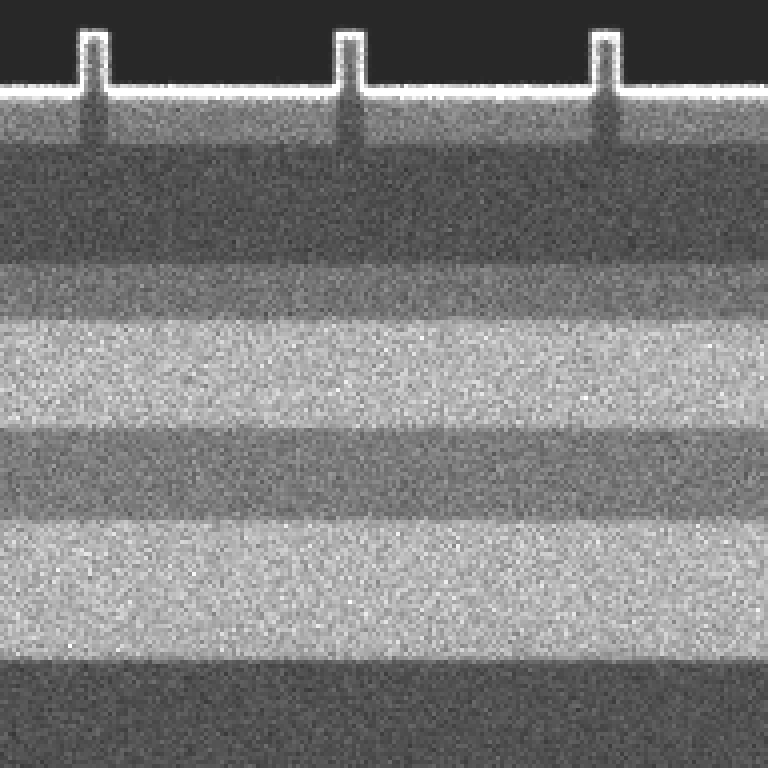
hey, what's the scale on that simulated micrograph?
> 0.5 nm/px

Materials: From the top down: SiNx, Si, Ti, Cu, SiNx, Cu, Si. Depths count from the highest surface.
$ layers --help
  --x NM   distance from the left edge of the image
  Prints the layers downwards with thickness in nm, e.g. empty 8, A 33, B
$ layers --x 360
empty 28, SiNx 28, Si 60, Ti 28, Cu 54, SiNx 46, Cu 70, Si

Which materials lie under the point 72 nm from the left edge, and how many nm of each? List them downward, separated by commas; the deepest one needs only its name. empty 28, SiNx 28, Si 60, Ti 28, Cu 54, SiNx 46, Cu 70, Si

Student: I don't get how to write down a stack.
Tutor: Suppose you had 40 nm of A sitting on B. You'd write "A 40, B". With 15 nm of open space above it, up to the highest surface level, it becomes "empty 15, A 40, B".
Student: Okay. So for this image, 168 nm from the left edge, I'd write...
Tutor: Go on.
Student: Si 116, Ti 28, Cu 54, SiNx 46, Cu 70, Si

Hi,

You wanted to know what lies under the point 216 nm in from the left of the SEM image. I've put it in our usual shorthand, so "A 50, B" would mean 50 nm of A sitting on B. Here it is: empty 28, SiNx 28, Si 60, Ti 28, Cu 54, SiNx 46, Cu 70, Si